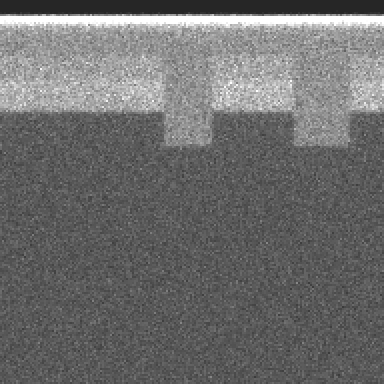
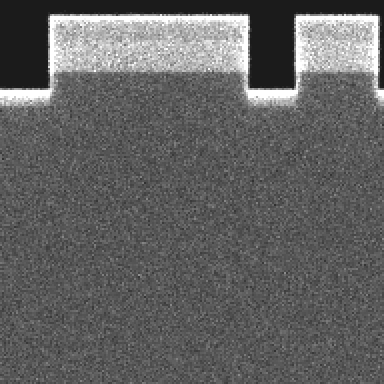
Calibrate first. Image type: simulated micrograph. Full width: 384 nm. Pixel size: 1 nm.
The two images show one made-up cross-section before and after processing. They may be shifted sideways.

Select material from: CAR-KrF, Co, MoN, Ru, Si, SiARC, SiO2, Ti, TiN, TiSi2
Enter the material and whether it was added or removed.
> SiARC / removed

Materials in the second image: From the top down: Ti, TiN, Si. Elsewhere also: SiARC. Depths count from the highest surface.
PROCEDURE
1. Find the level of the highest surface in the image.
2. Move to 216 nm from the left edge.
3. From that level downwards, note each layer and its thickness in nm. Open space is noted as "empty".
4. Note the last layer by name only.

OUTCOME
Ti 24, TiN 32, Si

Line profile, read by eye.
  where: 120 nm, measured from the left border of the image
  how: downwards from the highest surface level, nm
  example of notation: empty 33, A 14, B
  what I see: Ti 24, TiN 32, Si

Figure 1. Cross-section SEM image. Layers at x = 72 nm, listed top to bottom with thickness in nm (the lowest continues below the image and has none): Ti 24, TiN 32, Si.